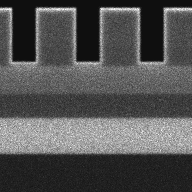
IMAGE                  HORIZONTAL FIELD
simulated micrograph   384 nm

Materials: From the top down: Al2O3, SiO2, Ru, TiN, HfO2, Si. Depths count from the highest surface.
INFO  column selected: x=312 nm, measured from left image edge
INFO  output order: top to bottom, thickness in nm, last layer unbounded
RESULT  empty 108, SiO2 8, Ru 56, TiN 48, HfO2 72, Si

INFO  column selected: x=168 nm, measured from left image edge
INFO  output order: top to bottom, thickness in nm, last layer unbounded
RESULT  empty 108, SiO2 8, Ru 56, TiN 48, HfO2 72, Si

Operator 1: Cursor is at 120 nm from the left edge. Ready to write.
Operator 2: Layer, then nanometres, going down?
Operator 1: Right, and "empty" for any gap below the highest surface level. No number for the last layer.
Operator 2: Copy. Al2O3 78, SiO2 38, Ru 56, TiN 48, HfO2 72, Si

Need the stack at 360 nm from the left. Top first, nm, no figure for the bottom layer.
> Al2O3 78, SiO2 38, Ru 56, TiN 48, HfO2 72, Si